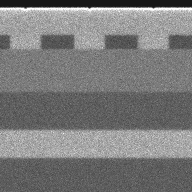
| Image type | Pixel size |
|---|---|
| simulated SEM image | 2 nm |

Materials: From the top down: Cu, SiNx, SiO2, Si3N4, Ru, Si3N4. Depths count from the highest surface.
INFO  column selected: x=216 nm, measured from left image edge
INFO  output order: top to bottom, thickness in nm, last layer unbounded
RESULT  Cu 54, SiNx 28, SiO2 86, Si3N4 76, Ru 56, Si3N4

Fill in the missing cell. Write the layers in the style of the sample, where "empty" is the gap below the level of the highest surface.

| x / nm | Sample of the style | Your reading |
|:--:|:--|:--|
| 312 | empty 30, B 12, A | Cu 82, SiO2 86, Si3N4 76, Ru 56, Si3N4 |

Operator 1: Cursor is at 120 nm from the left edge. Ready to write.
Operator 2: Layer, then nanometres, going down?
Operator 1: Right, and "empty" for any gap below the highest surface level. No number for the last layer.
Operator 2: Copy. Cu 54, SiNx 28, SiO2 86, Si3N4 76, Ru 56, Si3N4